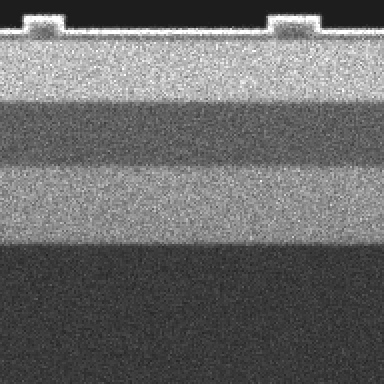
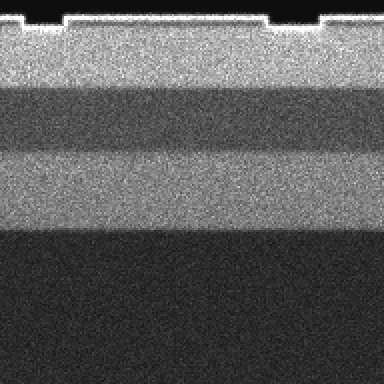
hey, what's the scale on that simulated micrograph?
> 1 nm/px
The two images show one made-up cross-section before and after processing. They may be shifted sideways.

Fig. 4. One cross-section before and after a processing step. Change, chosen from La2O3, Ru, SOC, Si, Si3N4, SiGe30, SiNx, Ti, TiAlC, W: SOC removed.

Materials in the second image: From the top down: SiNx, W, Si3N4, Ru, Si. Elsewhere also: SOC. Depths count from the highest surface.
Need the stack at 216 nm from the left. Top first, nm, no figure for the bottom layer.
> SiNx 10, W 62, Si3N4 64, Ru 78, Si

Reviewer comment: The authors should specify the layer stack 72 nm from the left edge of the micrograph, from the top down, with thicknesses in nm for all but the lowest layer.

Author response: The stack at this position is SiNx 10, W 62, Si3N4 64, Ru 78, Si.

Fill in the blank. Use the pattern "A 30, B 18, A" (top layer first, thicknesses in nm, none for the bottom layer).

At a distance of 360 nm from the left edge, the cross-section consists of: SiNx 10, W 62, Si3N4 64, Ru 78, Si